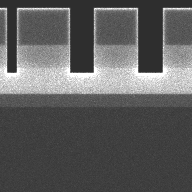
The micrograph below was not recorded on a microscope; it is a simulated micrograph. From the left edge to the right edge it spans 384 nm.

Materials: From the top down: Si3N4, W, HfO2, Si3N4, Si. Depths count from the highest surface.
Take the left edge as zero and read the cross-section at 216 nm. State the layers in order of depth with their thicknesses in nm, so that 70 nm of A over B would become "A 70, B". Si3N4 74, W 46, HfO2 52, Si3N4 26, Si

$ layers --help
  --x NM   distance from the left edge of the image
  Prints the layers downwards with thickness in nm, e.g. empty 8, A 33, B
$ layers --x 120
Si3N4 74, W 46, HfO2 52, Si3N4 26, Si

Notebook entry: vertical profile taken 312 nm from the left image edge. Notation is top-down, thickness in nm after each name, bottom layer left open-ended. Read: empty 130, HfO2 42, Si3N4 26, Si